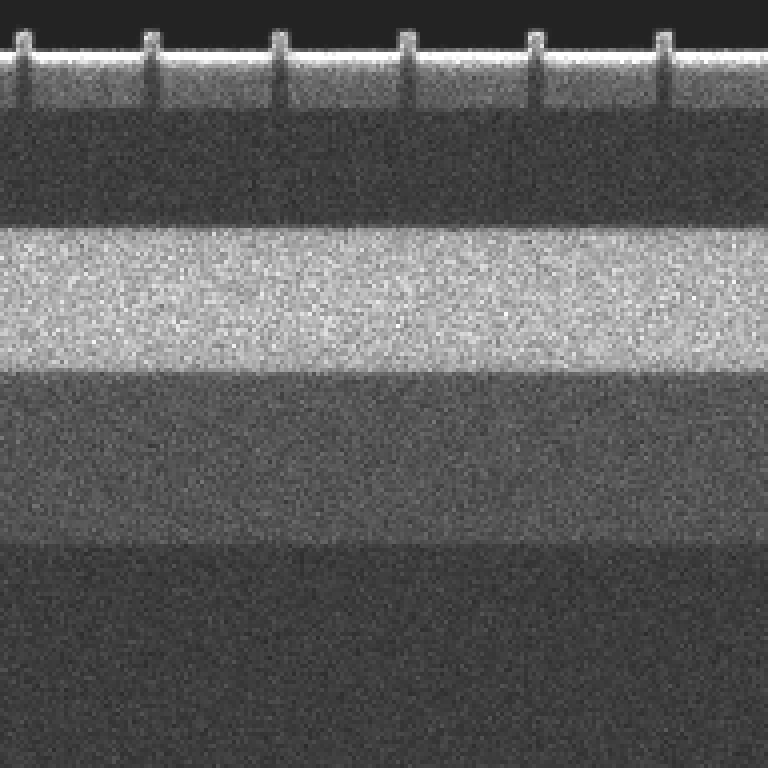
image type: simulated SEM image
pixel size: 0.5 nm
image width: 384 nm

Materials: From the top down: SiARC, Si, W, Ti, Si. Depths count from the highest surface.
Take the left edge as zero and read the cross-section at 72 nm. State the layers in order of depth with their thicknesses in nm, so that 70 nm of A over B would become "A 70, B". Si 98, W 72, Ti 86, Si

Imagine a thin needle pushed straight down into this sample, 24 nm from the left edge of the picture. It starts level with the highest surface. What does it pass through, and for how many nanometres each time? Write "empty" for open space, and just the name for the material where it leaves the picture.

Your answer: empty 10, SiARC 28, Si 60, W 72, Ti 86, Si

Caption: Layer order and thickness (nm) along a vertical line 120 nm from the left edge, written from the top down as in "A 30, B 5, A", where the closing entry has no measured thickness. empty 10, SiARC 28, Si 60, W 72, Ti 86, Si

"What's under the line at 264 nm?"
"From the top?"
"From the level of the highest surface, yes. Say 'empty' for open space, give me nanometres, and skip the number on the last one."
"Si 98, W 72, Ti 86, Si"